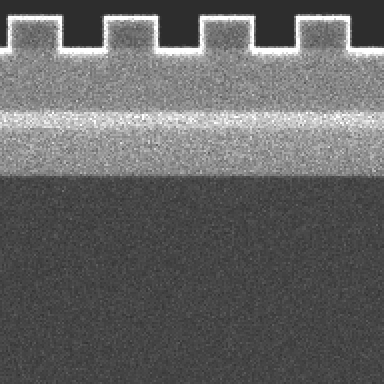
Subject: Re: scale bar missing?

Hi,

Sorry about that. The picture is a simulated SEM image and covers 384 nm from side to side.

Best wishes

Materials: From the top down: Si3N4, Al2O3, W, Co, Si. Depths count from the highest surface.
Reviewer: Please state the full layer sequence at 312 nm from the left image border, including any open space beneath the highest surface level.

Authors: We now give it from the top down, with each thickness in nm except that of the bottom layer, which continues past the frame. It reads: Si3N4 32, Al2O3 64, W 16, Co 48, Si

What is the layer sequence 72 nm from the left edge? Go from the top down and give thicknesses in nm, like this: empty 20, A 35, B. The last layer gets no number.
empty 32, Al2O3 64, W 16, Co 48, Si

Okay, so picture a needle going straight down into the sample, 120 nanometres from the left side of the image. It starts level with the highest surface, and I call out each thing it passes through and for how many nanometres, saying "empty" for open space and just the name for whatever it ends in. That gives Si3N4 32, Al2O3 64, W 16, Co 48, Si